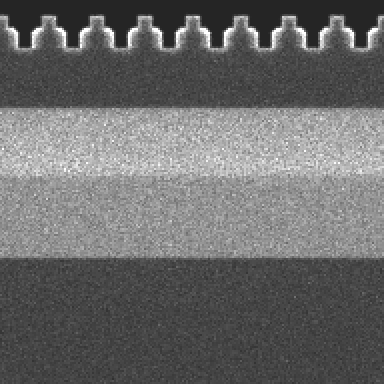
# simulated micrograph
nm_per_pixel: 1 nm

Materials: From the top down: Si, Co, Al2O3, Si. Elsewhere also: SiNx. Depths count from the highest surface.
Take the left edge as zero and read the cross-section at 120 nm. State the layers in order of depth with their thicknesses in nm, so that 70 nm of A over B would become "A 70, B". empty 32, Si 60, Co 68, Al2O3 82, Si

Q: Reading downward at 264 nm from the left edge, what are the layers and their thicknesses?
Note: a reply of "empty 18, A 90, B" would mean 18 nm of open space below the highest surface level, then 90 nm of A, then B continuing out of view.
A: empty 32, Si 60, Co 68, Al2O3 82, Si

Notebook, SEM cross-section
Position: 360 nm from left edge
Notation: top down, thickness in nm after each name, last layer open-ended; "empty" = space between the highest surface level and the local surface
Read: empty 32, Si 60, Co 68, Al2O3 82, Si